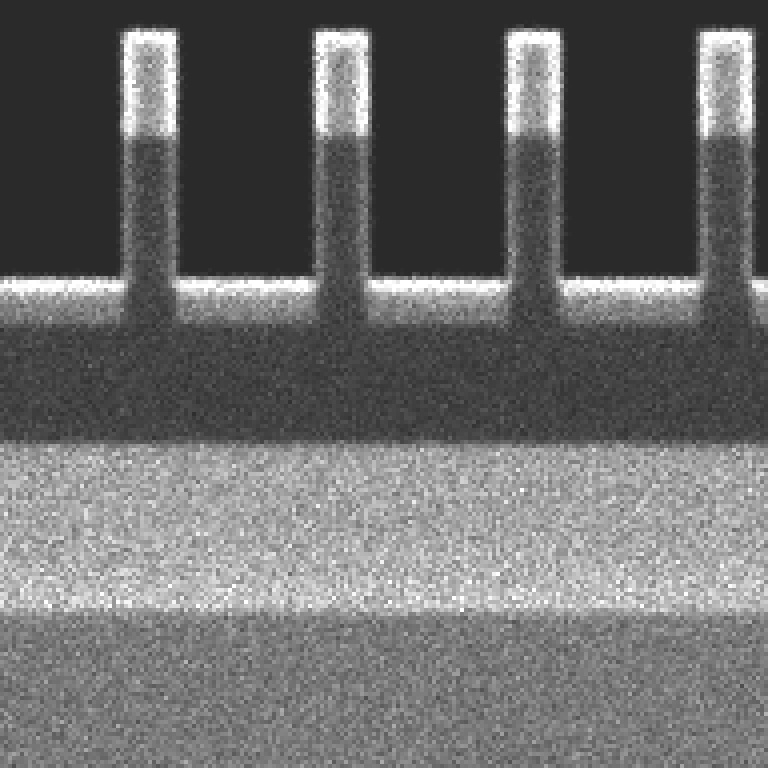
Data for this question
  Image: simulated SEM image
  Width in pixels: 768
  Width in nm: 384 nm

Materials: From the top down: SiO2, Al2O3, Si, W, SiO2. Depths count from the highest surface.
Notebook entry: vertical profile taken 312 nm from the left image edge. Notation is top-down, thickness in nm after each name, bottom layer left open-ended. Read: empty 124, SiO2 22, Si 60, W 84, SiO2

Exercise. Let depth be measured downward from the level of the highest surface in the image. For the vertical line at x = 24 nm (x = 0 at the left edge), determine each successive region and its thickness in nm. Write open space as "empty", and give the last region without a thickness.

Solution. empty 124, SiO2 22, Si 60, W 84, SiO2